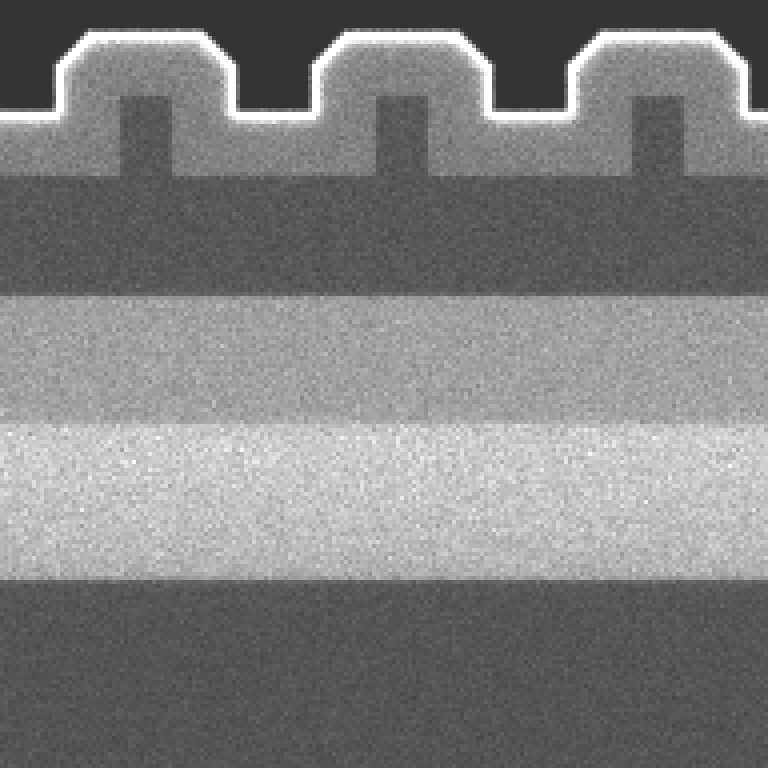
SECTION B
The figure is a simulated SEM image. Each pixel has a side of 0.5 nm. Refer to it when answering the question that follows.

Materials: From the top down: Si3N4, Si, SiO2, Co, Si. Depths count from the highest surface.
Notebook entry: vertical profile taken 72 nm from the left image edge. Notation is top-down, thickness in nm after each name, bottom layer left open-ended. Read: Si3N4 32, Si 100, SiO2 64, Co 78, Si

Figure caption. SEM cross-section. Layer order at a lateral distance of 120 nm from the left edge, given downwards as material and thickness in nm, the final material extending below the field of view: empty 40, Si3N4 32, Si 60, SiO2 64, Co 78, Si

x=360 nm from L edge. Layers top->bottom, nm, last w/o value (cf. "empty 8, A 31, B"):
empty 4, Si3N4 68, Si 60, SiO2 64, Co 78, Si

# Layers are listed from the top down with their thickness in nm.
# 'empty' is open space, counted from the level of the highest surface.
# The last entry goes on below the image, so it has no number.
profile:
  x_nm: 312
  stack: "Si3N4 72, Si 60, SiO2 64, Co 78, Si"